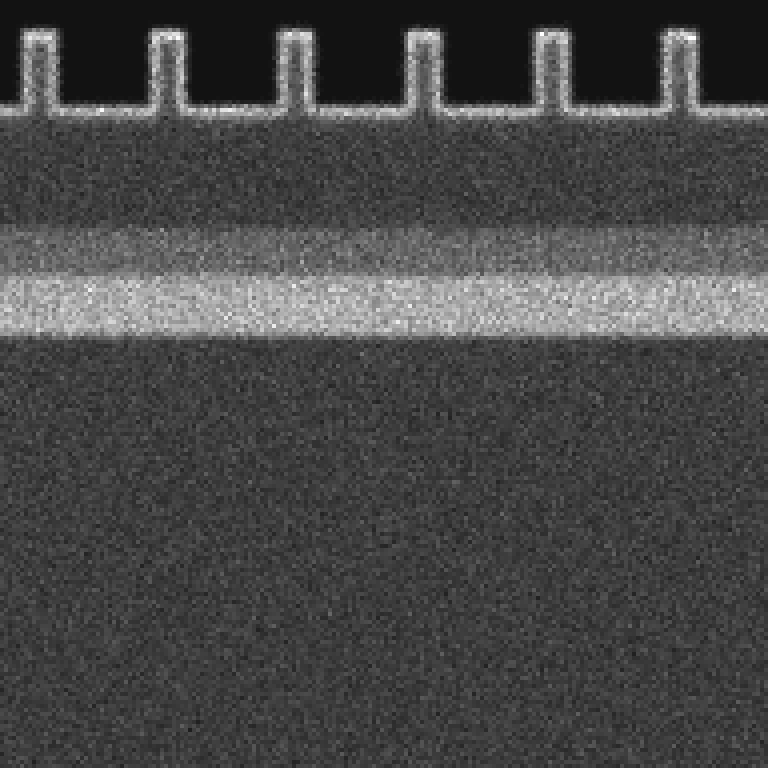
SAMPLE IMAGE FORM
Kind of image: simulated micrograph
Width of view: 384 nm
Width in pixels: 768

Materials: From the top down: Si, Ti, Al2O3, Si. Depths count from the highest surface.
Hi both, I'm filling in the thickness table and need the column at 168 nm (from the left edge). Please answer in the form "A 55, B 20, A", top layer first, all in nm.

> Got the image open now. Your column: empty 38, Si 60, Ti 24, Al2O3 30, Si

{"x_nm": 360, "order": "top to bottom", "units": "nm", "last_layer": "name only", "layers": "empty 38, Si 60, Ti 24, Al2O3 30, Si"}